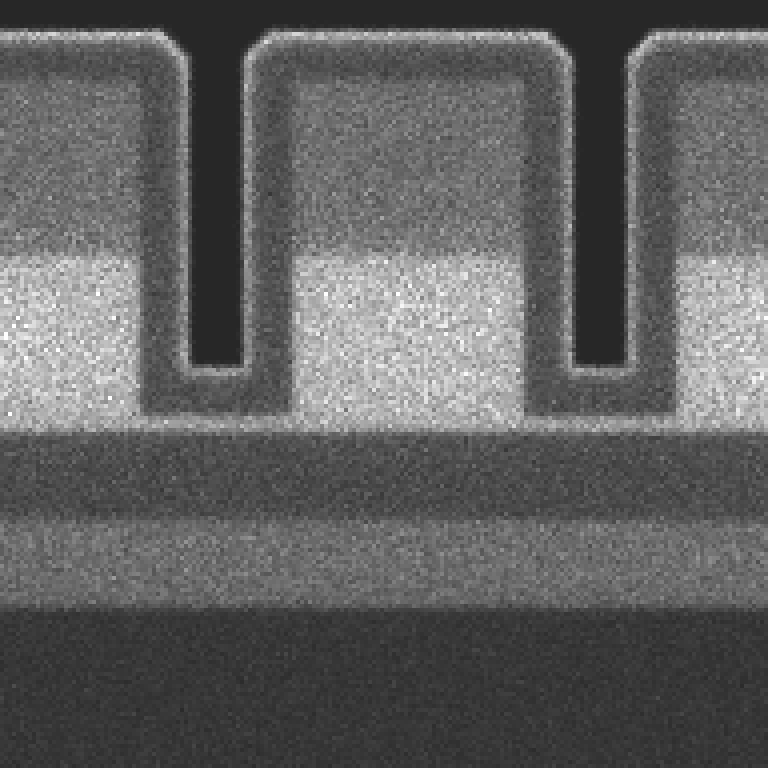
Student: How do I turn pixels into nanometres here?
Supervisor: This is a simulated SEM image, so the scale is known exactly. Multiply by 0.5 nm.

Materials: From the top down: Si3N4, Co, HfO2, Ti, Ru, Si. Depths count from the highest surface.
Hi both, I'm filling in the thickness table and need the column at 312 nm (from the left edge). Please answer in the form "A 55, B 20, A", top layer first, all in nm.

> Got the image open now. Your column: empty 168, Si3N4 24, HfO2 8, Ti 44, Ru 44, Si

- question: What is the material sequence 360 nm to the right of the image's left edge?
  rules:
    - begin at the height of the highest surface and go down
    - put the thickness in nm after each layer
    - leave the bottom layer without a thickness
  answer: Si3N4 24, Co 88, HfO2 88, Ti 44, Ru 44, Si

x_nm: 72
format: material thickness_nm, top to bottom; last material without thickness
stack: Si3N4 192, HfO2 8, Ti 44, Ru 44, Si